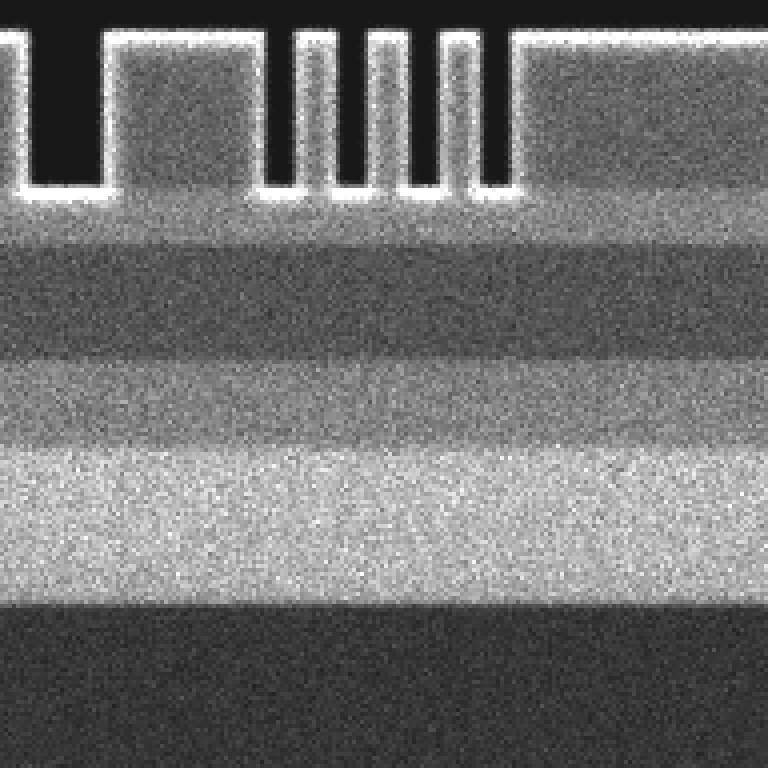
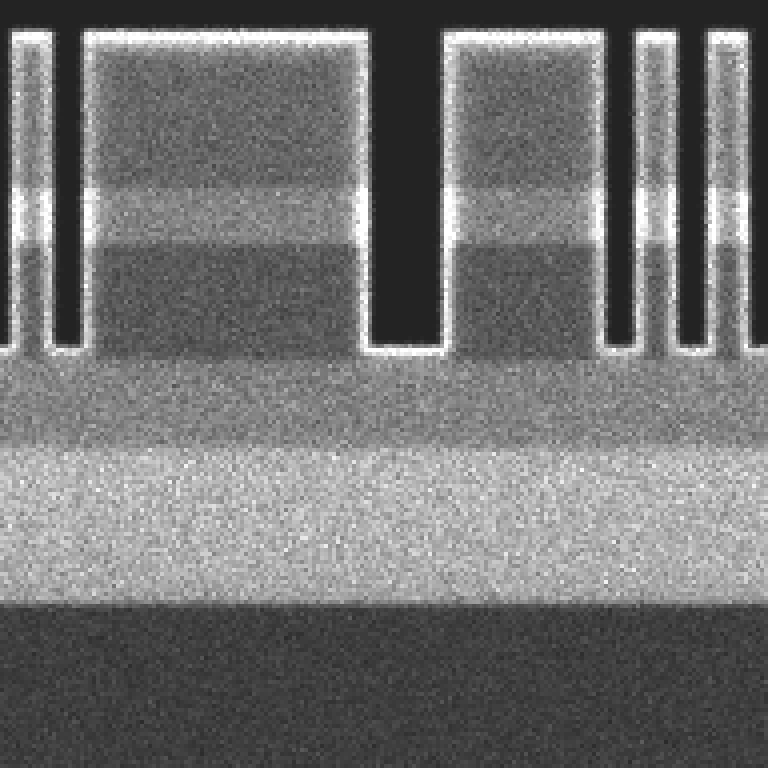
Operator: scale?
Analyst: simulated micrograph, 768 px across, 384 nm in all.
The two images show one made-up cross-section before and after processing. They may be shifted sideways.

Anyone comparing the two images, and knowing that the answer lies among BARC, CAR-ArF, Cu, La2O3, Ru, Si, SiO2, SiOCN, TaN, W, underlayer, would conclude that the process removed SiO2 and SiOCN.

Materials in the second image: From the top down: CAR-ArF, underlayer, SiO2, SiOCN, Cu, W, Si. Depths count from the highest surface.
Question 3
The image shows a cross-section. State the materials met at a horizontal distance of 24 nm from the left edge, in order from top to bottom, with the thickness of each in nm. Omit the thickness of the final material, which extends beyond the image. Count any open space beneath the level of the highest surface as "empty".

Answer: CAR-ArF 44, underlayer 34, SiO2 28, SiOCN 58, Cu 44, W 78, Si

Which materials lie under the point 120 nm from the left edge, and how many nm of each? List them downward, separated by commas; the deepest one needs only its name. CAR-ArF 44, underlayer 34, SiO2 28, SiOCN 58, Cu 44, W 78, Si